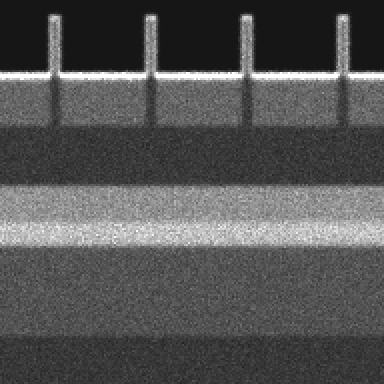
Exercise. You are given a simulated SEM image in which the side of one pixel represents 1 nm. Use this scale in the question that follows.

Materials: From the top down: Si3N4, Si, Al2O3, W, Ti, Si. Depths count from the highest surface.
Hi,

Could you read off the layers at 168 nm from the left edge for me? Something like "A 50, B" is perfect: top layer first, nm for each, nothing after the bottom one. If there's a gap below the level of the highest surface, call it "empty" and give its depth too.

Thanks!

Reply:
empty 58, Si3N4 52, Si 60, Al2O3 36, W 24, Ti 90, Si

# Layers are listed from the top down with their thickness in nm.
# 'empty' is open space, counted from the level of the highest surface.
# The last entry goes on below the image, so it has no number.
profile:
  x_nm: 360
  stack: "empty 58, Si3N4 52, Si 60, Al2O3 36, W 24, Ti 90, Si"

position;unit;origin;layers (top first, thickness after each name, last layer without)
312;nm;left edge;empty 58, Si3N4 52, Si 60, Al2O3 36, W 24, Ti 90, Si